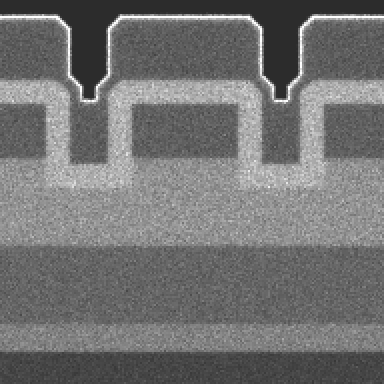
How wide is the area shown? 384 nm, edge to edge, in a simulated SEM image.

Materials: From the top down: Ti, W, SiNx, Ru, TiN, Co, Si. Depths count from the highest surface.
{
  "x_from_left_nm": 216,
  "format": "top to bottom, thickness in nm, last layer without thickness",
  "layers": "Ti 64, W 24, SiNx 54, Ru 88, TiN 78, Co 28, Si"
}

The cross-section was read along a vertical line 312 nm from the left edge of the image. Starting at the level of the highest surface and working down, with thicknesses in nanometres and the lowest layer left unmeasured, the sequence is Ti 64, W 108, Ru 58, TiN 78, Co 28, Si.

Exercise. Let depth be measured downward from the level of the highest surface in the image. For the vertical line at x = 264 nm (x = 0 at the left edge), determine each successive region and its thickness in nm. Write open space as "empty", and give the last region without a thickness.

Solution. empty 62, Ti 86, W 24, Ru 58, TiN 78, Co 28, Si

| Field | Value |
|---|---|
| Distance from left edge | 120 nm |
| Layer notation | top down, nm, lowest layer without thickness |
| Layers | Ti 64, W 108, Ru 58, TiN 78, Co 28, Si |